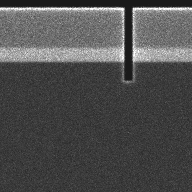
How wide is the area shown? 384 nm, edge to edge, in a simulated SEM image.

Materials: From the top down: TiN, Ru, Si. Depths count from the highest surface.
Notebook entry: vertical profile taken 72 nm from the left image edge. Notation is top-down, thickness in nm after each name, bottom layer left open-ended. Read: TiN 80, Ru 28, Si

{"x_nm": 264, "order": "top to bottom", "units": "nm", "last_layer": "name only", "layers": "empty 146, Si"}